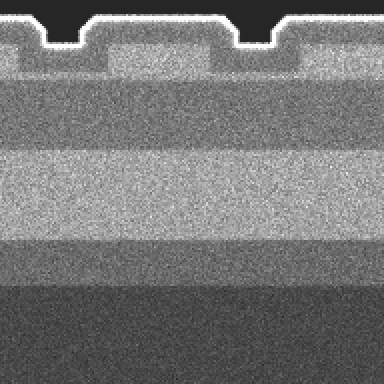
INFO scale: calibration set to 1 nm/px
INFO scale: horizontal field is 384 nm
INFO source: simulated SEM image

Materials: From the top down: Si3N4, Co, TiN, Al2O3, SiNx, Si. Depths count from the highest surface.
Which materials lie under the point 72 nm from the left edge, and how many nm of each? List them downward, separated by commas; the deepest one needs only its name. empty 28, Si3N4 28, Co 8, TiN 70, Al2O3 90, SiNx 46, Si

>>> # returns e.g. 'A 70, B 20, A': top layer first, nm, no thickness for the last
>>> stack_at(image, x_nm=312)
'Si3N4 28, Co 36, TiN 70, Al2O3 90, SiNx 46, Si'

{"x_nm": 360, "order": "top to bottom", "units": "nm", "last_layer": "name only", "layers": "Si3N4 28, Co 36, TiN 70, Al2O3 90, SiNx 46, Si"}